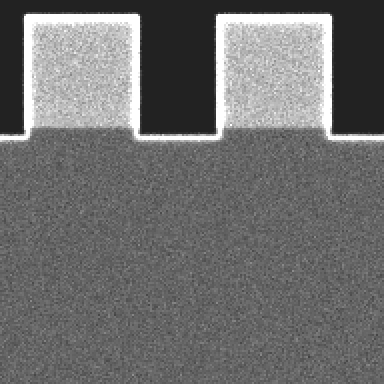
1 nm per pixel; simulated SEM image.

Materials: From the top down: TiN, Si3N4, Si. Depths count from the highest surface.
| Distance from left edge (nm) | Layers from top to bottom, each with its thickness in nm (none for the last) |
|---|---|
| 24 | empty 120, Si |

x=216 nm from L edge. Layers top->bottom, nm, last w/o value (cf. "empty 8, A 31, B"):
empty 120, Si